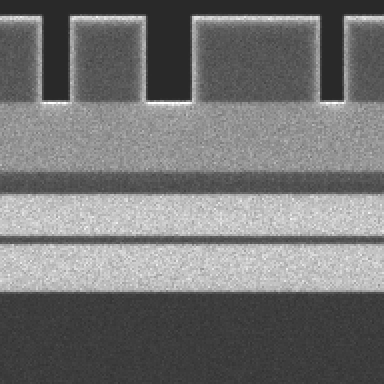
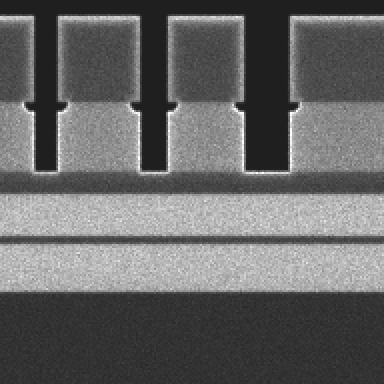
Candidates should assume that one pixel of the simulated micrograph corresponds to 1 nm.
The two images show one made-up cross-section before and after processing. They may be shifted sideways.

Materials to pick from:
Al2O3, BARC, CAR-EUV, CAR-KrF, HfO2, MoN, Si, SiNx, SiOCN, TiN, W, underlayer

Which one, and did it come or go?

W - removed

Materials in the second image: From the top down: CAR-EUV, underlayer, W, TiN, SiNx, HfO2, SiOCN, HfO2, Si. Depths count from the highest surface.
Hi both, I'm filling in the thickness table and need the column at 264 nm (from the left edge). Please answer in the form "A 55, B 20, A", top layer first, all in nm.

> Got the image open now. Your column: empty 156, TiN 10, SiNx 12, HfO2 42, SiOCN 8, HfO2 48, Si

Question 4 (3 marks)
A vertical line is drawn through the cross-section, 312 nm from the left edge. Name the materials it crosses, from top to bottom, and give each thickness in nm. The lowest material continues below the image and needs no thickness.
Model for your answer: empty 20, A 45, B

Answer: CAR-EUV 52, underlayer 34, W 70, TiN 10, SiNx 12, HfO2 42, SiOCN 8, HfO2 48, Si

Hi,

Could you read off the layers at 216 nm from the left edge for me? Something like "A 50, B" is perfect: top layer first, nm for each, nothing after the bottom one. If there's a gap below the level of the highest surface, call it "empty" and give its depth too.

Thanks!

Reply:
CAR-EUV 52, underlayer 34, W 70, TiN 10, SiNx 12, HfO2 42, SiOCN 8, HfO2 48, Si